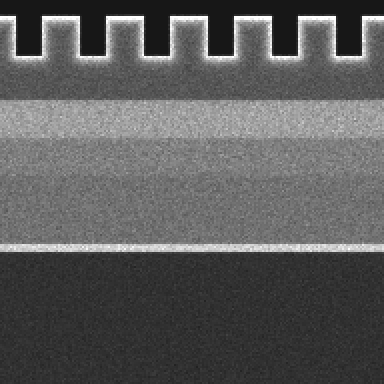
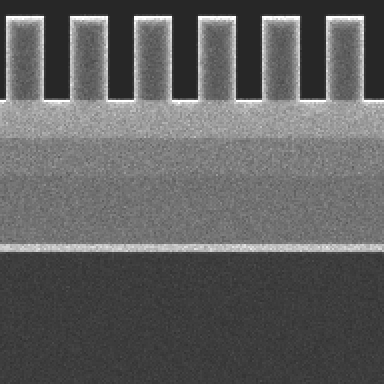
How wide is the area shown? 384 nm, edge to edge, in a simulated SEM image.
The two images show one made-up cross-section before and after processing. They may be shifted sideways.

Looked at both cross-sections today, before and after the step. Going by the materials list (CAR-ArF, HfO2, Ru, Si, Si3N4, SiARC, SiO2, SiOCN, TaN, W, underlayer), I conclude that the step removed underlayer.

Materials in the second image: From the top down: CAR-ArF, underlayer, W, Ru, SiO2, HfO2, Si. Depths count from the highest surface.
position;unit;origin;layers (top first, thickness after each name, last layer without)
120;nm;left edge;empty 84, W 38, Ru 38, SiO2 68, HfO2 8, Si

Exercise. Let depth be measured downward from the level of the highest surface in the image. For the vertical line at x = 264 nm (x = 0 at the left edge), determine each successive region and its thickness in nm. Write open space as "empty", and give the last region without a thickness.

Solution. CAR-ArF 40, underlayer 44, W 38, Ru 38, SiO2 68, HfO2 8, Si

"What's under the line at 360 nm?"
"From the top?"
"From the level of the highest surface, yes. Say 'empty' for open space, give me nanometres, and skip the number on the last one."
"CAR-ArF 40, underlayer 44, W 38, Ru 38, SiO2 68, HfO2 8, Si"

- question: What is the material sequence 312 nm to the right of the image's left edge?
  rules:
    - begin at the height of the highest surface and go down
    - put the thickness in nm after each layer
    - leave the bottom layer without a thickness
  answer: empty 84, W 38, Ru 38, SiO2 68, HfO2 8, Si